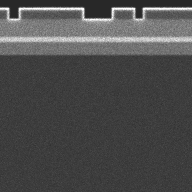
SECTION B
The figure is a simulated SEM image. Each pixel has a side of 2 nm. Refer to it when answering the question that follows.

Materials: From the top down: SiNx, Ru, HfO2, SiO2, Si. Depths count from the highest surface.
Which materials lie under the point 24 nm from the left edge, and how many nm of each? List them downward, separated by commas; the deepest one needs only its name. empty 22, Ru 36, HfO2 10, SiO2 26, Si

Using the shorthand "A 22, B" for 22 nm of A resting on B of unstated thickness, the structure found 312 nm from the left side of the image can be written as SiNx 22, Ru 36, HfO2 10, SiO2 26, Si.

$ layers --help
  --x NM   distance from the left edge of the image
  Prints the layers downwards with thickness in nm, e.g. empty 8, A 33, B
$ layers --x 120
SiNx 22, Ru 36, HfO2 10, SiO2 26, Si